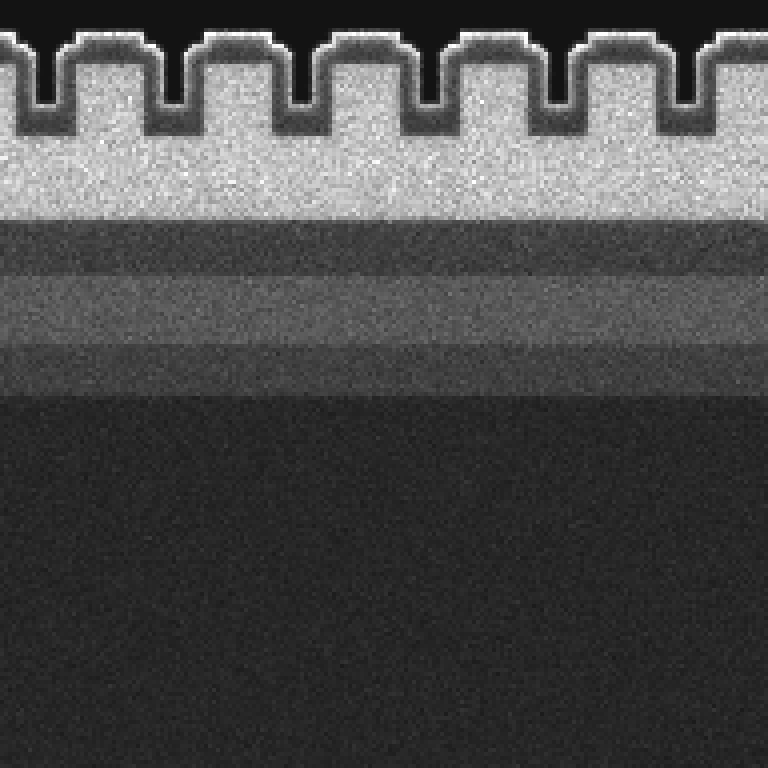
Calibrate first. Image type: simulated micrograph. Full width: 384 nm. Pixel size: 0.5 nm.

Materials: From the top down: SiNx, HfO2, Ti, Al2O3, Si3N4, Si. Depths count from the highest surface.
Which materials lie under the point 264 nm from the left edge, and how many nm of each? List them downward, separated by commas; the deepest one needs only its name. empty 6, SiNx 46, HfO2 42, Ti 28, Al2O3 34, Si3N4 26, Si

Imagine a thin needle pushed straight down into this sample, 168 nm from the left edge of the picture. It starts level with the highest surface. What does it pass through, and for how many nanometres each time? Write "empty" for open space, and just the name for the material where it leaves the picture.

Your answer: SiNx 16, HfO2 78, Ti 28, Al2O3 34, Si3N4 26, Si